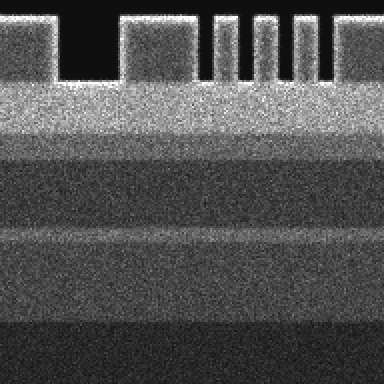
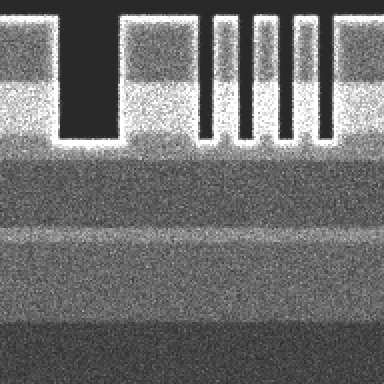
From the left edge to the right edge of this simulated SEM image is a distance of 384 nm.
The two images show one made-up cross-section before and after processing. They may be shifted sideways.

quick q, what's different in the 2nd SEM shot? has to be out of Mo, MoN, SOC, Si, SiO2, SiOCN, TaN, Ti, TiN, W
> SiO2 and W removed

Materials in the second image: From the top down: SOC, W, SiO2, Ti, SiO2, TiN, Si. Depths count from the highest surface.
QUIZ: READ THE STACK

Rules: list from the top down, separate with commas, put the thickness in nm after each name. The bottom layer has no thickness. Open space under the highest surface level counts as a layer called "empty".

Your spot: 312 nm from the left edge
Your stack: SOC 66, W 52, SiO2 26, Ti 68, SiO2 14, TiN 80, Si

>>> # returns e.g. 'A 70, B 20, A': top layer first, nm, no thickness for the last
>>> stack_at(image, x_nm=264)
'SOC 66, W 52, SiO2 26, Ti 68, SiO2 14, TiN 80, Si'